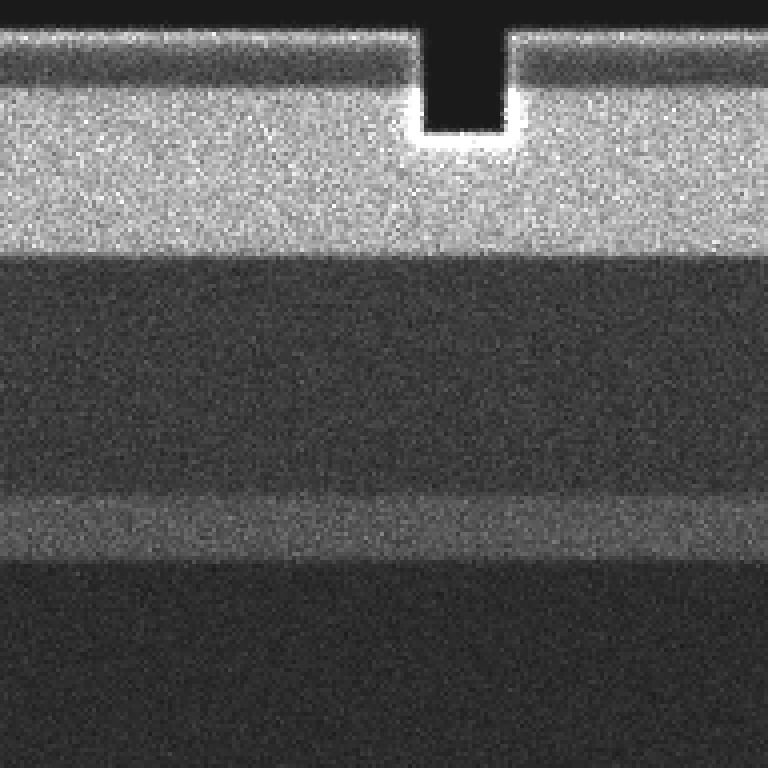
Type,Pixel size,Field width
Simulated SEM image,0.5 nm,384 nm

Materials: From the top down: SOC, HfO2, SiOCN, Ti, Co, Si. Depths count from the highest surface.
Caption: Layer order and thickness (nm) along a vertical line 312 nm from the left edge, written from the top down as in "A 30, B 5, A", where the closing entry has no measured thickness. SOC 28, HfO2 84, SiOCN 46, Ti 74, Co 32, Si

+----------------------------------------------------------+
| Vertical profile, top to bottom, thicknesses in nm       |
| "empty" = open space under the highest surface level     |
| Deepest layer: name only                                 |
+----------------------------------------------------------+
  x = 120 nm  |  SOC 28, HfO2 84, SiOCN 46, Ti 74, Co 32, Si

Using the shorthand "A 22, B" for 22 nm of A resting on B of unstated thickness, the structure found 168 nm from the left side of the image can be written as SOC 28, HfO2 84, SiOCN 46, Ti 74, Co 32, Si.